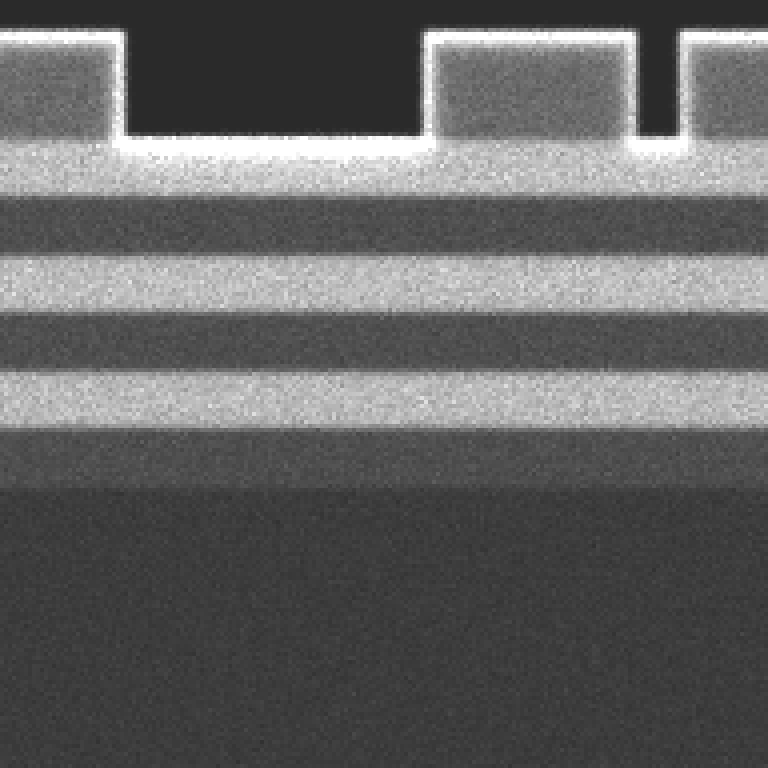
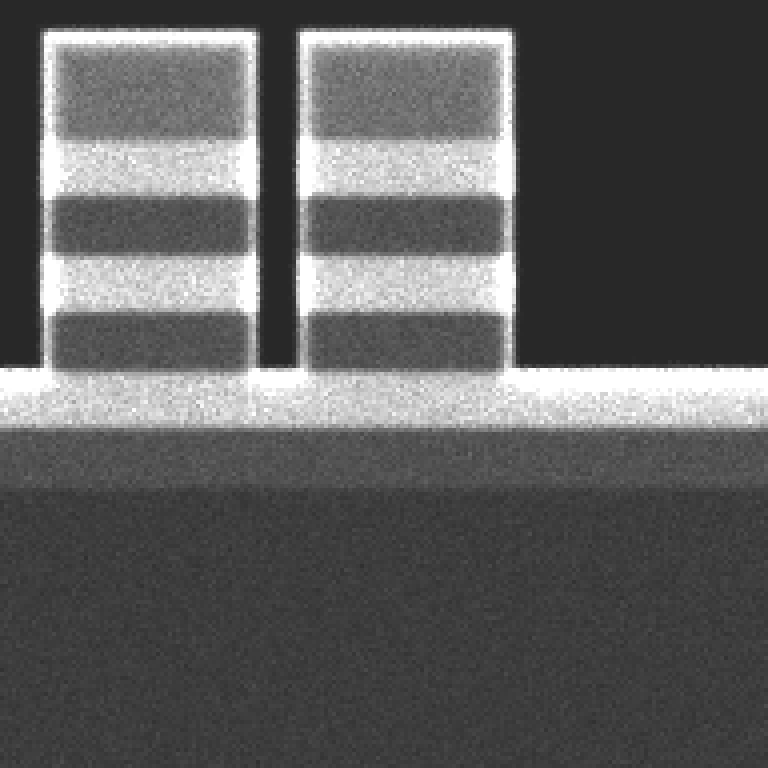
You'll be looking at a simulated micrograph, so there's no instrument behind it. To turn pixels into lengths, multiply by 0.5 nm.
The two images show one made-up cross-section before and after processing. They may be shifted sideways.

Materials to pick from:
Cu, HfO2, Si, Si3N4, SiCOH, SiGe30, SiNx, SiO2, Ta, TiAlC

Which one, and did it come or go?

HfO2 and SiNx - removed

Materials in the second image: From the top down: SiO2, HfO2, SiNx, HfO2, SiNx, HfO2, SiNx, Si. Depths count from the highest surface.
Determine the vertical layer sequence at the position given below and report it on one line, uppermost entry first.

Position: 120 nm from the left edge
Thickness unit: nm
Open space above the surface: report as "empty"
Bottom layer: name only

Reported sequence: SiO2 54, HfO2 28, SiNx 30, HfO2 28, SiNx 30, HfO2 28, SiNx 30, Si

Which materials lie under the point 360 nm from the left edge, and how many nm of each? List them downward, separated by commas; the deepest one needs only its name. empty 170, HfO2 28, SiNx 30, Si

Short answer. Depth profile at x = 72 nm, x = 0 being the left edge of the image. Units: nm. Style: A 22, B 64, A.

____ SiO2 54, HfO2 28, SiNx 30, HfO2 28, SiNx 30, HfO2 28, SiNx 30, Si